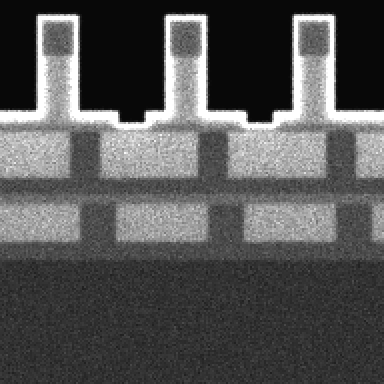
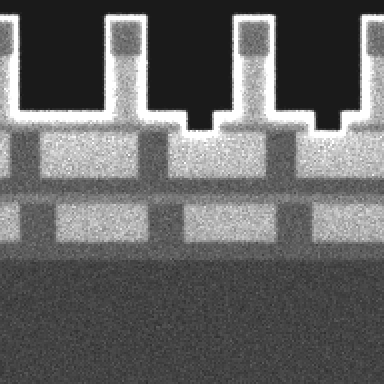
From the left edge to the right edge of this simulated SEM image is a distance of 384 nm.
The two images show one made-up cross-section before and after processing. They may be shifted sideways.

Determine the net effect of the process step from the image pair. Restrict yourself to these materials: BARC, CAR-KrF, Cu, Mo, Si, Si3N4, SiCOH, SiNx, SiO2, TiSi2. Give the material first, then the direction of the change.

Si3N4: removed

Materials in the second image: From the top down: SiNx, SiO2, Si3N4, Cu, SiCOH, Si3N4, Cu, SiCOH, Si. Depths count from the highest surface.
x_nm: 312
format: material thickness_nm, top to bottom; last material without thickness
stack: empty 96, SiO2 12, Si3N4 8, Cu 46, SiCOH 16, Si3N4 10, Cu 38, SiCOH 18, Si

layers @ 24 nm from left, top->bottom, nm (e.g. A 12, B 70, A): empty 96, SiO2 12, Si3N4 8, SiCOH 62, Si3N4 10, SiCOH 56, Si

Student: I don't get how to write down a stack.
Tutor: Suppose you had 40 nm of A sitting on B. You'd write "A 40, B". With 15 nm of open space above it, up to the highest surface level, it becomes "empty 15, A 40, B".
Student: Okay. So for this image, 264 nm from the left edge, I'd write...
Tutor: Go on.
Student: SiNx 40, SiO2 68, Si3N4 8, Cu 46, SiCOH 16, Si3N4 10, Cu 38, SiCOH 18, Si